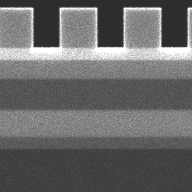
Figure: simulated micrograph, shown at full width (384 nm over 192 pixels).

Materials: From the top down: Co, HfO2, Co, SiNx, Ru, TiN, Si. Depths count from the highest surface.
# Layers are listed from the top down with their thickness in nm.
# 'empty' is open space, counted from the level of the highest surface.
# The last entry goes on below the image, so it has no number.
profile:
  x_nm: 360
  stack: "empty 80, HfO2 24, Co 38, SiNx 62, Ru 54, TiN 24, Si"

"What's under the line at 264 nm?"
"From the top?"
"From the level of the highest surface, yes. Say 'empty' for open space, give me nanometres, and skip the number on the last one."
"Co 80, HfO2 24, Co 38, SiNx 62, Ru 54, TiN 24, Si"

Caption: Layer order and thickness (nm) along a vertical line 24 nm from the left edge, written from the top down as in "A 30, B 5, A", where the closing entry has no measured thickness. Co 80, HfO2 24, Co 38, SiNx 62, Ru 54, TiN 24, Si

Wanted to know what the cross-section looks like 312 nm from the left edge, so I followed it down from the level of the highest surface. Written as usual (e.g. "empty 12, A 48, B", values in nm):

Co 80, HfO2 24, Co 38, SiNx 62, Ru 54, TiN 24, Si